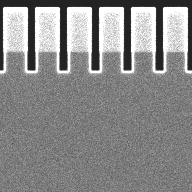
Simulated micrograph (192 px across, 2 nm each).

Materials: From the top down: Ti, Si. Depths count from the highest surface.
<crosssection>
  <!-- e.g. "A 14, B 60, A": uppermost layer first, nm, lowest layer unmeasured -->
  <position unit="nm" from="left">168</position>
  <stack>Ti 88, Si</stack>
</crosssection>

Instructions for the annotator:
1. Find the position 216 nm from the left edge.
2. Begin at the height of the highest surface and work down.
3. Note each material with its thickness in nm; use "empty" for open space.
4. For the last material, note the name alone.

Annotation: Ti 88, Si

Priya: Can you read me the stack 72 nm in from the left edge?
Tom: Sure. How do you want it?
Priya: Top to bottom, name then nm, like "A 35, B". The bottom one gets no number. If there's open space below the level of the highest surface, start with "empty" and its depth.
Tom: Ti 88, Si